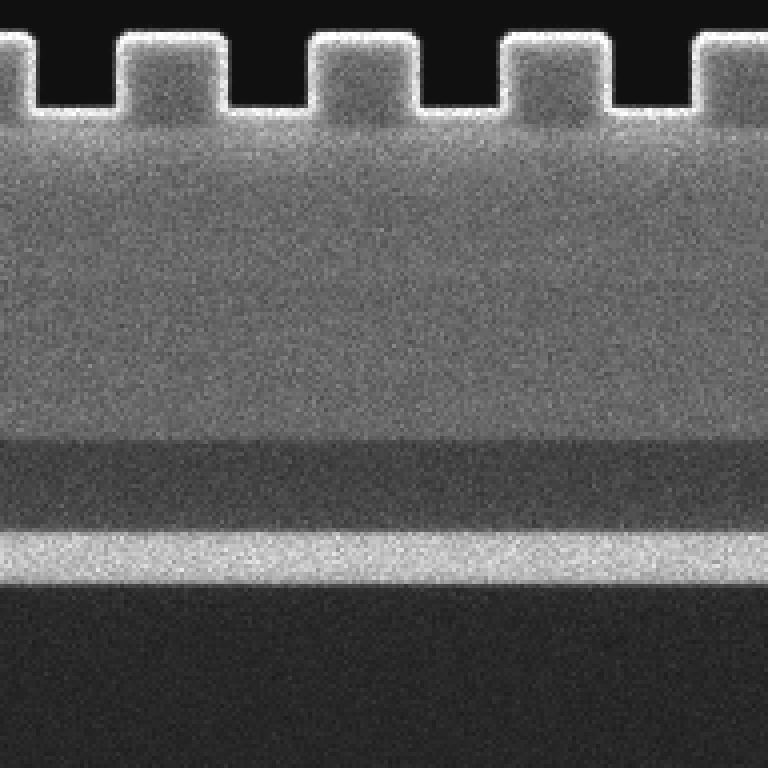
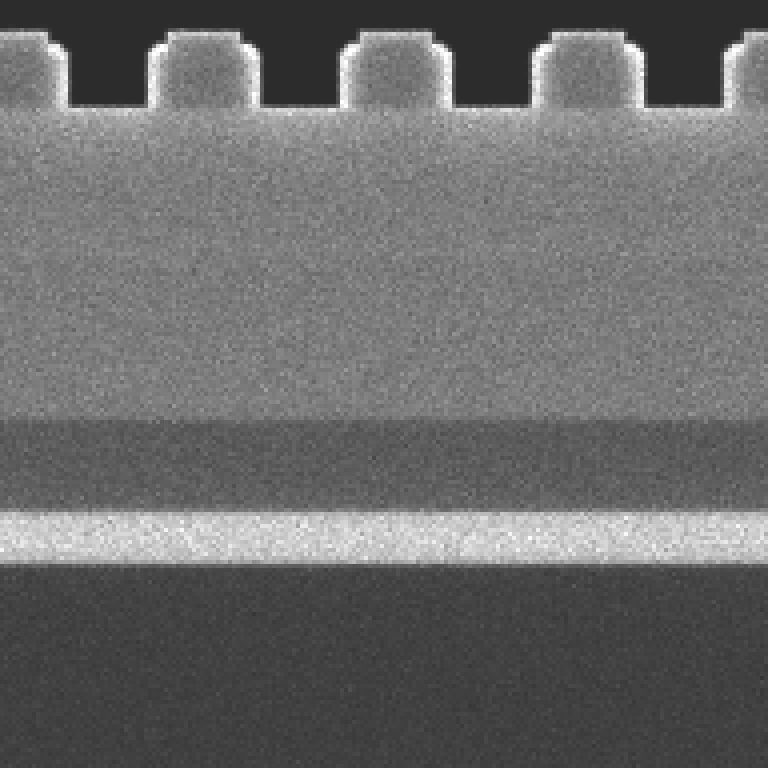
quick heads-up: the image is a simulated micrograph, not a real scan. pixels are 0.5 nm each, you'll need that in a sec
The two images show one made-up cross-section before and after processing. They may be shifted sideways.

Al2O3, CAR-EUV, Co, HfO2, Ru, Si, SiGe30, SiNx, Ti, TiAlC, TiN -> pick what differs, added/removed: Al2O3 removed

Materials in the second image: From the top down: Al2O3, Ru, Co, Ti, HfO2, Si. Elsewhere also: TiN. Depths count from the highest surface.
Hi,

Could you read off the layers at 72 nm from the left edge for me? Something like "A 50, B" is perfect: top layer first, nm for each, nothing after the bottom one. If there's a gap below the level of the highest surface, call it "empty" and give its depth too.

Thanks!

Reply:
empty 38, Ru 76, Co 80, Ti 46, HfO2 26, Si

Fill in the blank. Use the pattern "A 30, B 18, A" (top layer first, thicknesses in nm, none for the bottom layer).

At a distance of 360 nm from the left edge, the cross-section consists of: empty 38, Ru 76, Co 80, Ti 46, HfO2 26, Si